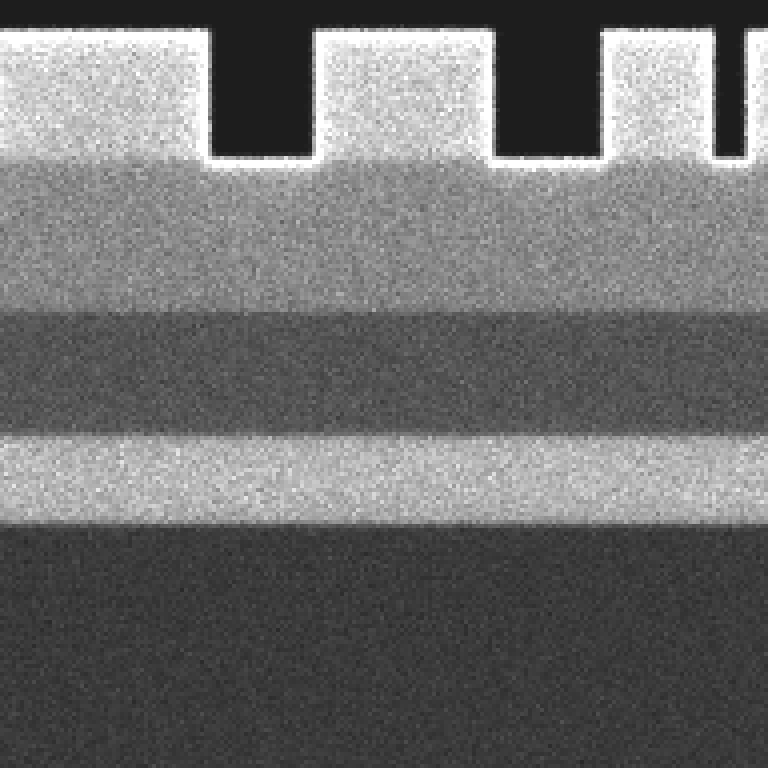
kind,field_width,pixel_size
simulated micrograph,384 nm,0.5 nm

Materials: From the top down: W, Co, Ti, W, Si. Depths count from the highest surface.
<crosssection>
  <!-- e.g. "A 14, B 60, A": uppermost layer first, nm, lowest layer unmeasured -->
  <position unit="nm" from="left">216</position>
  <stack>W 64, Co 76, Ti 62, W 44, Si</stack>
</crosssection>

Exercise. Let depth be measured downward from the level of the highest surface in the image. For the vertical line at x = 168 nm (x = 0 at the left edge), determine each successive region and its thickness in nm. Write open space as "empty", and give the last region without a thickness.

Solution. W 64, Co 76, Ti 62, W 44, Si